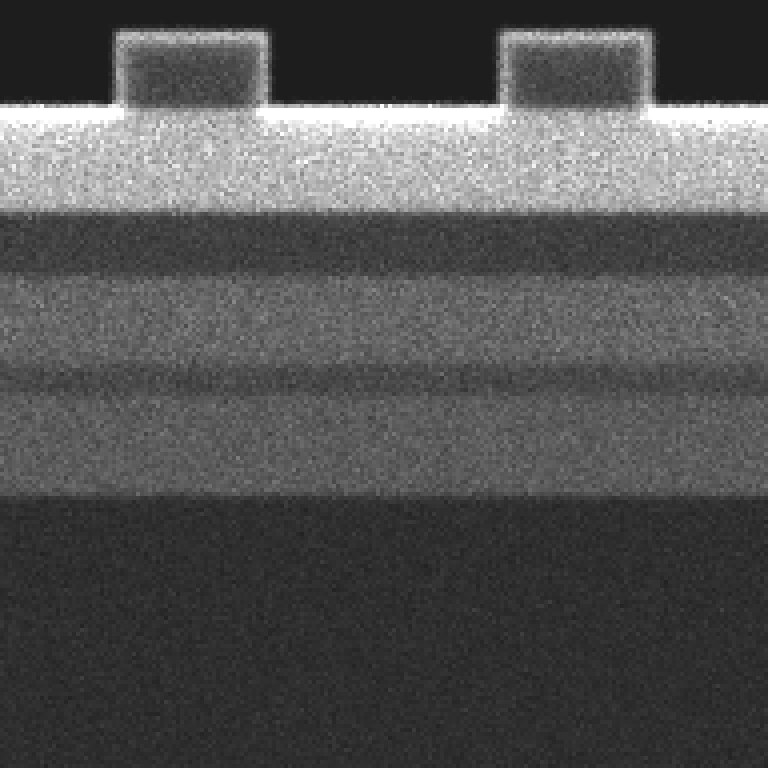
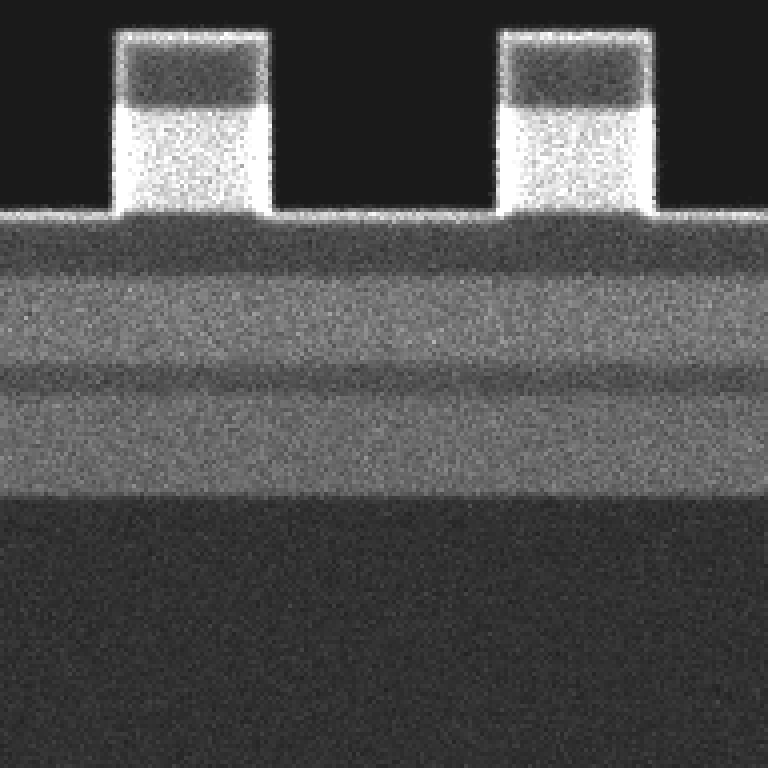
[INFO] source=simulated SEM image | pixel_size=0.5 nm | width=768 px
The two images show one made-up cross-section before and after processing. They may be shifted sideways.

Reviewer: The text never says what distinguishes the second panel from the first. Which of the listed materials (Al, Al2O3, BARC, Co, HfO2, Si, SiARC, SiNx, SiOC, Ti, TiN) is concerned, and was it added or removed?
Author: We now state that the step removed HfO2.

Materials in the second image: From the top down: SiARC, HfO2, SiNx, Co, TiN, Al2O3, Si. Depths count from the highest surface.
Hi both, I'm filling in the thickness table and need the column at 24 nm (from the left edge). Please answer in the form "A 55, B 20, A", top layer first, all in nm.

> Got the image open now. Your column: empty 90, SiNx 32, Co 44, TiN 16, Al2O3 50, Si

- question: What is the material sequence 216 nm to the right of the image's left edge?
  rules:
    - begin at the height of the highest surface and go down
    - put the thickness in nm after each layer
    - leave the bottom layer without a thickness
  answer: empty 90, SiNx 32, Co 44, TiN 16, Al2O3 50, Si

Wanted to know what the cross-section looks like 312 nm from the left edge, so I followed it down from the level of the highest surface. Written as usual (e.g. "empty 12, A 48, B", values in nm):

SiARC 38, HfO2 52, SiNx 32, Co 44, TiN 16, Al2O3 50, Si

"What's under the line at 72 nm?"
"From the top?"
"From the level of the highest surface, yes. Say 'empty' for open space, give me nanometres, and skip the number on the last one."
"SiARC 38, HfO2 52, SiNx 32, Co 44, TiN 16, Al2O3 50, Si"